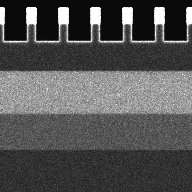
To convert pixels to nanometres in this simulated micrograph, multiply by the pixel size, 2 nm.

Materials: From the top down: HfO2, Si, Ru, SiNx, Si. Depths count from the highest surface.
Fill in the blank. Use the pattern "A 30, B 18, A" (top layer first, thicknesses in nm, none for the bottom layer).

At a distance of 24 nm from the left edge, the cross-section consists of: empty 66, Si 60, Ru 86, SiNx 72, Si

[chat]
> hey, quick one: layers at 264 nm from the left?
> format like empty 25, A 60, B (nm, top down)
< empty 66, Si 60, Ru 86, SiNx 72, Si